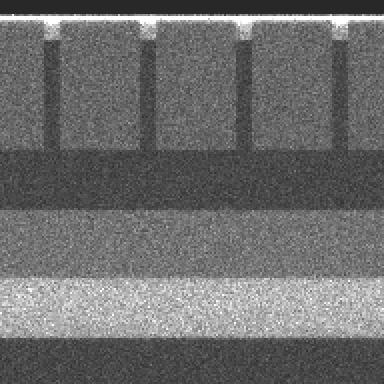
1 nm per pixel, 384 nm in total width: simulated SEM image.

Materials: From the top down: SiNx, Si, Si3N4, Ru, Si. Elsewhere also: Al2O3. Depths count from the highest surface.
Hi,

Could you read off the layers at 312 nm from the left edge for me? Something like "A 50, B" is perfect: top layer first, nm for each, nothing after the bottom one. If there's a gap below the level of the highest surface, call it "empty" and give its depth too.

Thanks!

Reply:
SiNx 134, Si 60, Si3N4 68, Ru 60, Si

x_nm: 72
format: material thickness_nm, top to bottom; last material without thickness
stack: SiNx 134, Si 60, Si3N4 68, Ru 60, Si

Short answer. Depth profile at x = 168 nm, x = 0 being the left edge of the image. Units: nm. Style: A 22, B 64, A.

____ SiNx 134, Si 60, Si3N4 68, Ru 60, Si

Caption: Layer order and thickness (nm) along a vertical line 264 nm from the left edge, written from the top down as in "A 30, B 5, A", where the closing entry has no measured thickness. SiNx 134, Si 60, Si3N4 68, Ru 60, Si